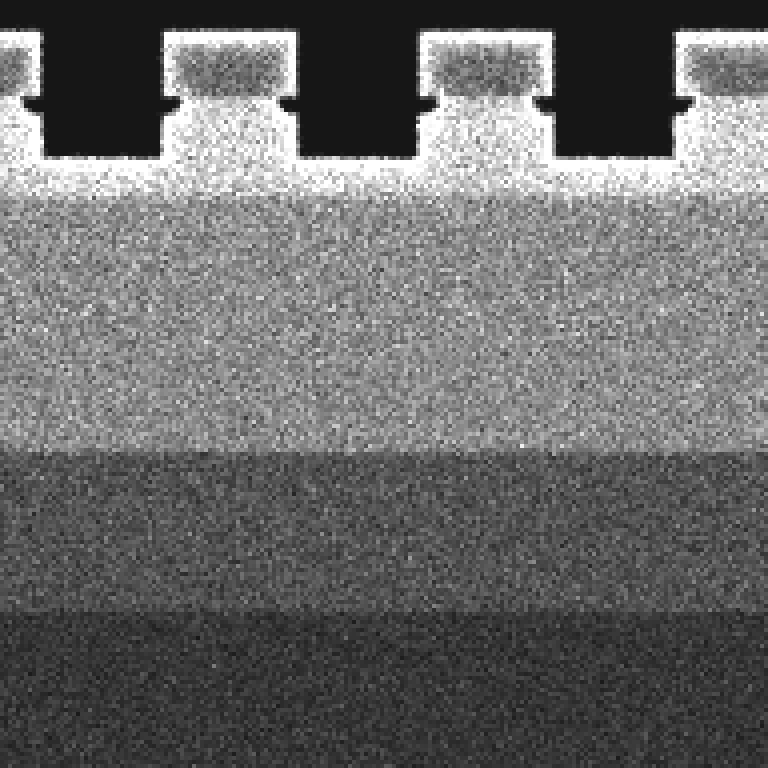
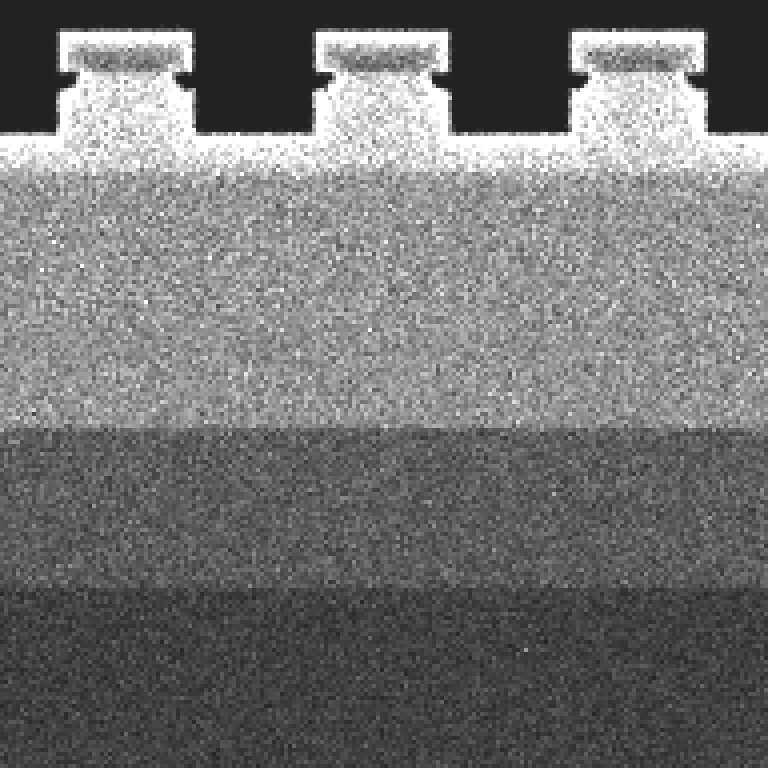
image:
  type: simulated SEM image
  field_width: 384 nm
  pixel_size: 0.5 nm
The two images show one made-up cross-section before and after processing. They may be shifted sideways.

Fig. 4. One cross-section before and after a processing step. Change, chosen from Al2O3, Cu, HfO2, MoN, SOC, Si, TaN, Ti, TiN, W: SOC removed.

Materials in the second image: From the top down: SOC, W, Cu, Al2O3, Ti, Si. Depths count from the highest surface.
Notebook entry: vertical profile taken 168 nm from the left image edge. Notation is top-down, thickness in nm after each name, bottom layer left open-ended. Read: SOC 20, W 50, Cu 72, Al2O3 56, Ti 80, Si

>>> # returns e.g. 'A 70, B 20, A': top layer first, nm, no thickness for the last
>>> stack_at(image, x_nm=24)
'empty 52, W 18, Cu 72, Al2O3 56, Ti 80, Si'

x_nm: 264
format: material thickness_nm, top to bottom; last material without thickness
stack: empty 52, W 18, Cu 72, Al2O3 56, Ti 80, Si